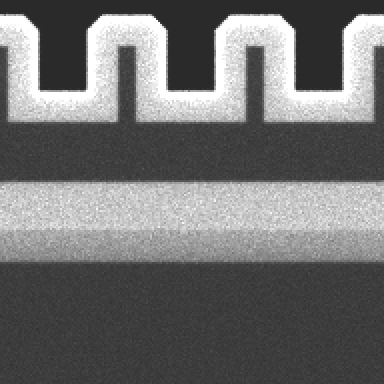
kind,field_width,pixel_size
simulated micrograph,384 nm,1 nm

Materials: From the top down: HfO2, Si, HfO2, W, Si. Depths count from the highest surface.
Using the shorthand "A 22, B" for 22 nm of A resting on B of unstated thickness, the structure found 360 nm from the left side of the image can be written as HfO2 106, Si 60, HfO2 48, W 32, Si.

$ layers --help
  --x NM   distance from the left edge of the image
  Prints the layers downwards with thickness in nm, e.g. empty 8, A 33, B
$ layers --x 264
HfO2 106, Si 60, HfO2 48, W 32, Si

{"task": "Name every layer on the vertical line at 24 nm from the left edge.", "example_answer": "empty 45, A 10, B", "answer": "empty 2, HfO2 104, Si 60, HfO2 48, W 32, Si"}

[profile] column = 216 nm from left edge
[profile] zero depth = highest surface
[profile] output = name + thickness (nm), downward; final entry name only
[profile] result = empty 14, HfO2 92, Si 60, HfO2 48, W 32, Si